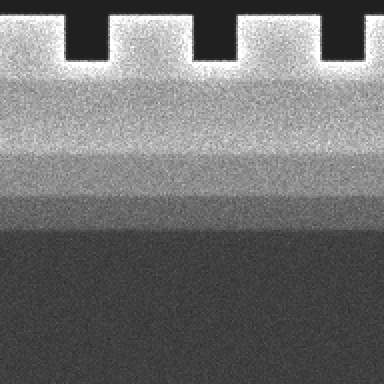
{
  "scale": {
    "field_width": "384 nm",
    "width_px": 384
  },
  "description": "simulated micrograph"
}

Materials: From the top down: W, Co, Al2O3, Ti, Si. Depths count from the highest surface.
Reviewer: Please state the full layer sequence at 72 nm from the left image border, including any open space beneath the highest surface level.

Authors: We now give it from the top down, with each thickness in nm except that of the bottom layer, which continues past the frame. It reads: empty 46, W 18, Co 74, Al2O3 42, Ti 34, Si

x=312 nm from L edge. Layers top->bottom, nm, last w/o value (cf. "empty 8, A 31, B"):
W 64, Co 74, Al2O3 42, Ti 34, Si